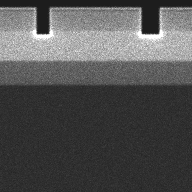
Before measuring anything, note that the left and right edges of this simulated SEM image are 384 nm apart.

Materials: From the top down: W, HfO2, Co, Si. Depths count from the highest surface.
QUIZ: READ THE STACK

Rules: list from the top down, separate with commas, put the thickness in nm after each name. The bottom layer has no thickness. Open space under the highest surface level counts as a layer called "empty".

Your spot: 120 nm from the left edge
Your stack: W 46, HfO2 60, Co 48, Si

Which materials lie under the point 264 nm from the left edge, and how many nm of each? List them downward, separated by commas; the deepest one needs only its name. W 46, HfO2 60, Co 48, Si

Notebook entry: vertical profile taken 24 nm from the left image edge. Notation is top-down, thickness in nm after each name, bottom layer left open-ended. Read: W 46, HfO2 60, Co 48, Si